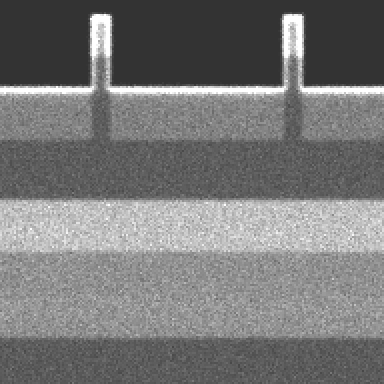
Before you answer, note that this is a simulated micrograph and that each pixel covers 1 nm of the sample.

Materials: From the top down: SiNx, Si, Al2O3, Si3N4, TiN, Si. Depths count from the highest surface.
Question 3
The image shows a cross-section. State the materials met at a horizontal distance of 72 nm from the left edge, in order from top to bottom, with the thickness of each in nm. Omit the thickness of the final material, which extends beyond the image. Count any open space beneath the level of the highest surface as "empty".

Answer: empty 72, SiNx 52, Si 60, Al2O3 52, Si3N4 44, TiN 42, Si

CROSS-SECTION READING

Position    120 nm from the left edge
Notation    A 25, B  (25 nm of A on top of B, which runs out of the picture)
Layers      empty 72, SiNx 52, Si 60, Al2O3 52, Si3N4 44, TiN 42, Si